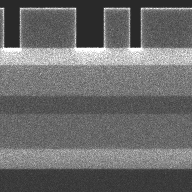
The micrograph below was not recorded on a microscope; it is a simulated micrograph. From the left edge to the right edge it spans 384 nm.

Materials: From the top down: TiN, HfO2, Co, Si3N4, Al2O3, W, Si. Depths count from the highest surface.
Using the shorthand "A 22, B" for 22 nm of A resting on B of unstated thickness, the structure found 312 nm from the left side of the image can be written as TiN 80, HfO2 34, Co 62, Si3N4 36, Al2O3 70, W 40, Si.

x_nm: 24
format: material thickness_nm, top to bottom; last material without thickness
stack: empty 80, HfO2 34, Co 62, Si3N4 36, Al2O3 70, W 40, Si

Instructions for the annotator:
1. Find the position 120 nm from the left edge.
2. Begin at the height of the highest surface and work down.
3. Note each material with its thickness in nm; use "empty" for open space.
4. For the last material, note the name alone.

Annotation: TiN 80, HfO2 34, Co 62, Si3N4 36, Al2O3 70, W 40, Si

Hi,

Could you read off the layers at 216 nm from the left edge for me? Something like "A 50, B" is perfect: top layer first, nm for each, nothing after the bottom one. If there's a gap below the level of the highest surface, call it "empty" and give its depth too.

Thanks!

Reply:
TiN 80, HfO2 34, Co 62, Si3N4 36, Al2O3 70, W 40, Si